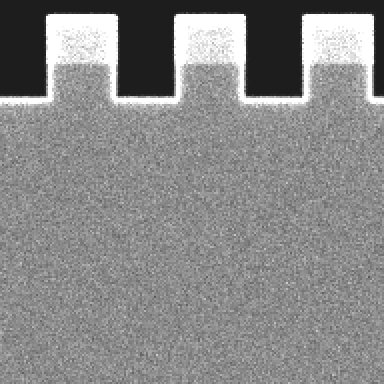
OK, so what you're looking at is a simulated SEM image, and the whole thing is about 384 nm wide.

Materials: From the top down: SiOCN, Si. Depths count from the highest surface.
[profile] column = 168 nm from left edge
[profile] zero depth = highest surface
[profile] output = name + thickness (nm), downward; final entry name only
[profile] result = empty 82, Si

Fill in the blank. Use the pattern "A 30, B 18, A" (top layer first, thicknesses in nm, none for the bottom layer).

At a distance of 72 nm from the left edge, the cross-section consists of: SiOCN 48, Si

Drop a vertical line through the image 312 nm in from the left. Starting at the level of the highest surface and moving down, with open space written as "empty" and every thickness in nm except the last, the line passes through SiOCN 48, Si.